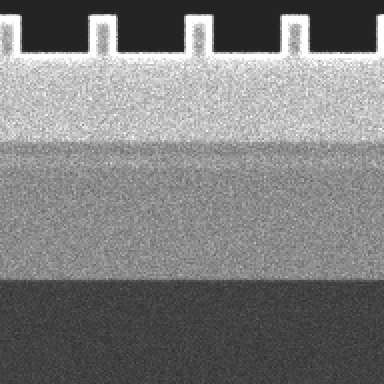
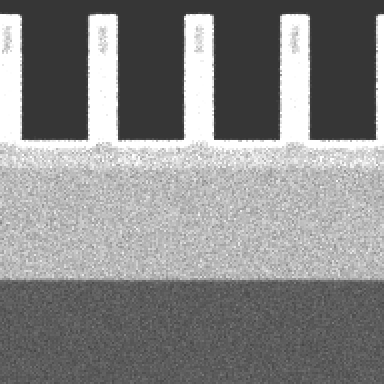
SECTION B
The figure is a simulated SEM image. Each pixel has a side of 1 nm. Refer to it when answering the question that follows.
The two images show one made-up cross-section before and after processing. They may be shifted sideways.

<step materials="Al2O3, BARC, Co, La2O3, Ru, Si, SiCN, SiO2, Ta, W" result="removed W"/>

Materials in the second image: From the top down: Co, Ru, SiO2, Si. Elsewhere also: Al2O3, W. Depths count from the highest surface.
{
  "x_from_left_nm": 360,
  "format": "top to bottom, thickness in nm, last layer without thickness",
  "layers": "empty 126, Co 14, Ru 12, SiO2 112, Si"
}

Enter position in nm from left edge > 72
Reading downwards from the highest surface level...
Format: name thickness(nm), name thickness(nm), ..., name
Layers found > empty 126, Co 14, Ru 12, SiO2 112, Si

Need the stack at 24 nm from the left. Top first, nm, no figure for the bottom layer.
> empty 126, Co 14, Ru 12, SiO2 112, Si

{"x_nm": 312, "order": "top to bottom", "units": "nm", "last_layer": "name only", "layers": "empty 126, Co 14, Ru 12, SiO2 112, Si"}